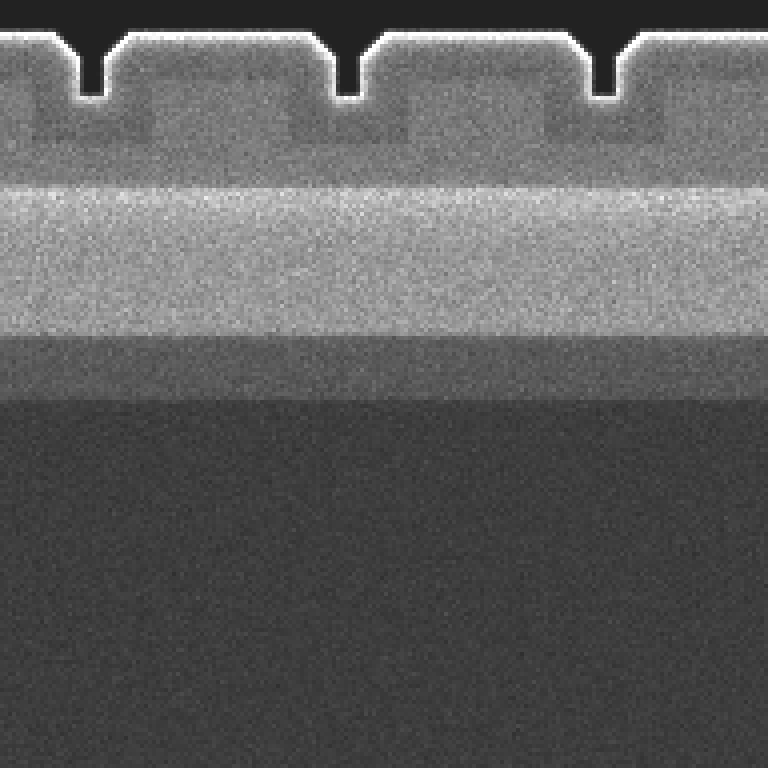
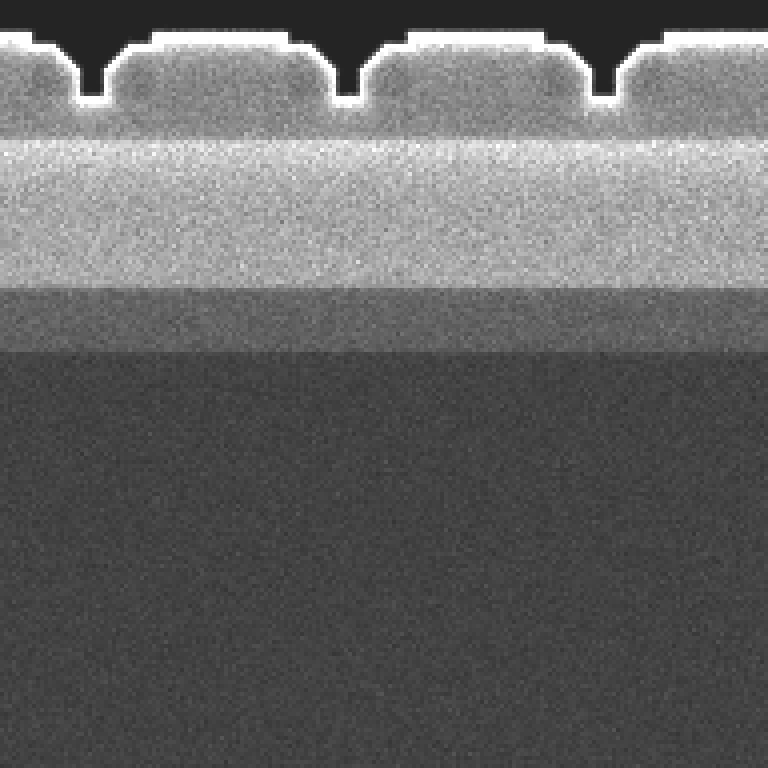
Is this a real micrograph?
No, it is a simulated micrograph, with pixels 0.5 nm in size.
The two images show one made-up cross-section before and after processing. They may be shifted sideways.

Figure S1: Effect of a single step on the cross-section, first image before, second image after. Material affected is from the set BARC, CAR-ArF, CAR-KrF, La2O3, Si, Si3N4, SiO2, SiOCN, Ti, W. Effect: removed Si3N4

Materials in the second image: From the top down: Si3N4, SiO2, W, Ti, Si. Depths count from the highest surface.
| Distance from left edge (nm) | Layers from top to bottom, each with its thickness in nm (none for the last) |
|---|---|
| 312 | empty 14, Si3N4 18, SiO2 22, W 74, Ti 32, Si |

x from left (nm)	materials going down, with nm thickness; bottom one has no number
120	SiO2 54, W 74, Ti 32, Si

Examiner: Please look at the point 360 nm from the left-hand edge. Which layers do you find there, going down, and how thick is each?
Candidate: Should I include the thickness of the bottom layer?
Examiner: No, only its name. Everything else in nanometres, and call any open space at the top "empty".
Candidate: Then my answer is SiO2 54, W 74, Ti 32, Si